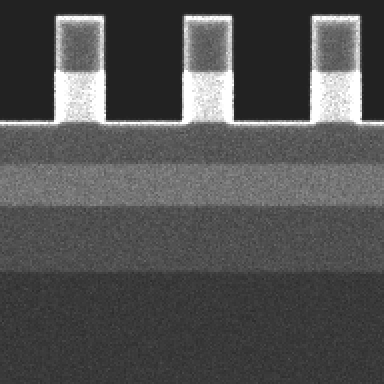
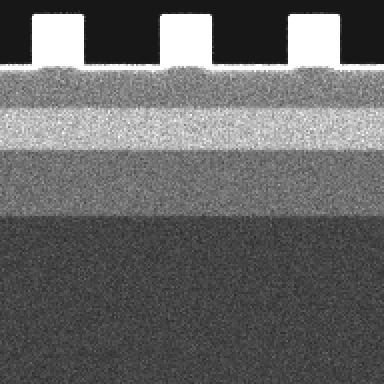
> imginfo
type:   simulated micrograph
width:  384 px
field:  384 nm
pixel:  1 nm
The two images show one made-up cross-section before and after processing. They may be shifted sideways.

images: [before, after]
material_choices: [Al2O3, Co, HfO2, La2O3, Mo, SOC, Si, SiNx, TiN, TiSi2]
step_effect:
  removed: SOC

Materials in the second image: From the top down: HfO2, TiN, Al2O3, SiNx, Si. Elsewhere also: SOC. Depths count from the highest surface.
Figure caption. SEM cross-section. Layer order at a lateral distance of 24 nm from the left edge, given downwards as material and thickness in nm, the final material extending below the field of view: empty 50, TiN 42, Al2O3 42, SiNx 66, Si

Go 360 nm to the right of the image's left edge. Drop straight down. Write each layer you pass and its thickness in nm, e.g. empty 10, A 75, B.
empty 50, TiN 42, Al2O3 42, SiNx 66, Si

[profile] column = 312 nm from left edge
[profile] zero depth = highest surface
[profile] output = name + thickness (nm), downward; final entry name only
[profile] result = HfO2 50, TiN 42, Al2O3 42, SiNx 66, Si